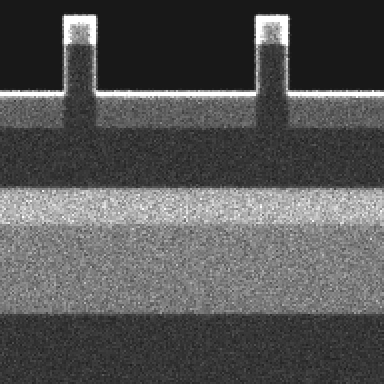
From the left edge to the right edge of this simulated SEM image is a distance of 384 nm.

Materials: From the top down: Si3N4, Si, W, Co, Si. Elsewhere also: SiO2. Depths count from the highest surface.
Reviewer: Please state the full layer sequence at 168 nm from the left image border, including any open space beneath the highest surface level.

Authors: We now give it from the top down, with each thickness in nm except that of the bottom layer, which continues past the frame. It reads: empty 76, Si3N4 36, Si 60, W 36, Co 90, Si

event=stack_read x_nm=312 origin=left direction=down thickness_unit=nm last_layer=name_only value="empty 76, Si3N4 36, Si 60, W 36, Co 90, Si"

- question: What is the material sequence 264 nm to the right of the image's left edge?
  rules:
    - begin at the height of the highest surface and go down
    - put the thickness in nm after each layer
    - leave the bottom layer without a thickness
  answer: SiO2 28, Si 144, W 36, Co 90, Si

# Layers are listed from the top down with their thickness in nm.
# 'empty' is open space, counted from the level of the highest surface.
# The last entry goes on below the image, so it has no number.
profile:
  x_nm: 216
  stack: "empty 76, Si3N4 36, Si 60, W 36, Co 90, Si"